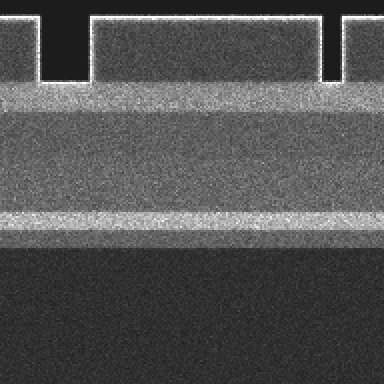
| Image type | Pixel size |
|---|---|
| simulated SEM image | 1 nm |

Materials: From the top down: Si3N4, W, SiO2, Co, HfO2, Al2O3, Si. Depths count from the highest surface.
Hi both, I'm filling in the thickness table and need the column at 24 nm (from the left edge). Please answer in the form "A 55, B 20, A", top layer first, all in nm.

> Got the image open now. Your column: Si3N4 66, W 30, SiO2 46, Co 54, HfO2 18, Al2O3 18, Si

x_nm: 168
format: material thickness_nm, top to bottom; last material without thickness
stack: Si3N4 66, W 30, SiO2 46, Co 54, HfO2 18, Al2O3 18, Si